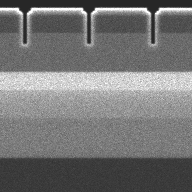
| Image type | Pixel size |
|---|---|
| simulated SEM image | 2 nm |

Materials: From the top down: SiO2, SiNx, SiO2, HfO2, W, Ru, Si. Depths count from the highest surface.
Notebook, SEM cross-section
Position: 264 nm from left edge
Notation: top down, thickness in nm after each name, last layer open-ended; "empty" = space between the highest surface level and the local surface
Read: SiO2 14, SiNx 36, SiO2 78, HfO2 36, W 56, Ru 80, Si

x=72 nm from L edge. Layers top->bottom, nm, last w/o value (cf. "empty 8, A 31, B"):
SiO2 14, SiNx 36, SiO2 78, HfO2 36, W 56, Ru 80, Si